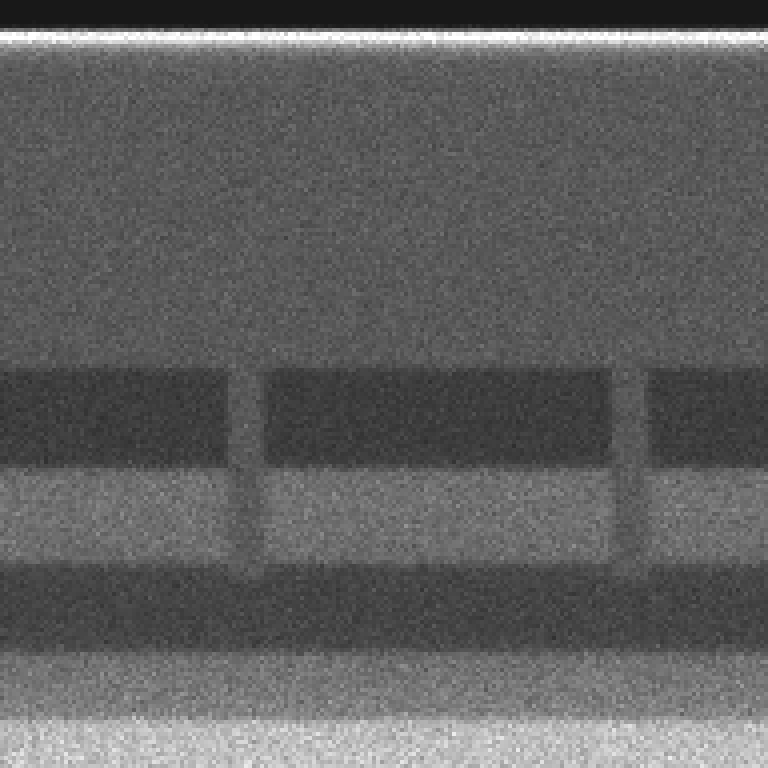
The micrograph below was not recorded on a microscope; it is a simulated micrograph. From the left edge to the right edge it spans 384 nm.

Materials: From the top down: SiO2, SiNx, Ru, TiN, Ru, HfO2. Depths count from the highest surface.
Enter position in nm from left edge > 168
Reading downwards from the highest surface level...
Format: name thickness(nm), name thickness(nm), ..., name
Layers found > SiO2 168, SiNx 50, Ru 48, TiN 44, Ru 34, HfO2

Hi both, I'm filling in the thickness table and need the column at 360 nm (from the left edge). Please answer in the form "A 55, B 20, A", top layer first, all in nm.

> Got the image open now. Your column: SiO2 168, SiNx 50, Ru 48, TiN 44, Ru 34, HfO2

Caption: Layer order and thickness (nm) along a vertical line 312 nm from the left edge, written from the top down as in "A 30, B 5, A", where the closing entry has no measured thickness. SiO2 274, TiN 36, Ru 34, HfO2